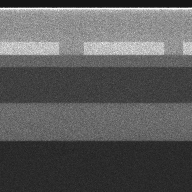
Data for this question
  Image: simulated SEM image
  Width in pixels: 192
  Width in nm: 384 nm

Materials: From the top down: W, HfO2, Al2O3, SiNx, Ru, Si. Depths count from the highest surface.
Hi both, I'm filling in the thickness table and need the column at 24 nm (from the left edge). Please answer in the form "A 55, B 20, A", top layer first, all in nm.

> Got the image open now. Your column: W 68, HfO2 26, Al2O3 24, SiNx 72, Ru 76, Si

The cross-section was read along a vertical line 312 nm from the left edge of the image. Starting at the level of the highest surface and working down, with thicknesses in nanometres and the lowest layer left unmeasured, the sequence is W 68, HfO2 26, Al2O3 24, SiNx 72, Ru 76, Si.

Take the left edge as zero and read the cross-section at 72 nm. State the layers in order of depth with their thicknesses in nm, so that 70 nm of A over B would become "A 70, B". W 68, HfO2 26, Al2O3 24, SiNx 72, Ru 76, Si